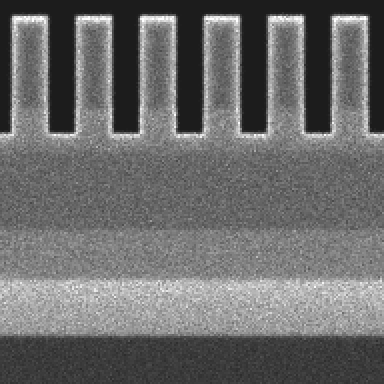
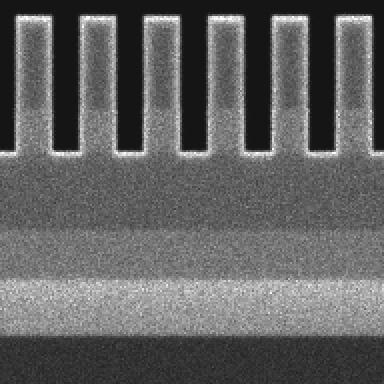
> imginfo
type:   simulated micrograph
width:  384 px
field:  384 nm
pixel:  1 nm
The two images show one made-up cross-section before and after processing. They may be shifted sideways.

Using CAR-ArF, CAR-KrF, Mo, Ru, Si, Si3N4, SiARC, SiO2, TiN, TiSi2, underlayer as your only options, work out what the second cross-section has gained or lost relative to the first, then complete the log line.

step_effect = removed TiN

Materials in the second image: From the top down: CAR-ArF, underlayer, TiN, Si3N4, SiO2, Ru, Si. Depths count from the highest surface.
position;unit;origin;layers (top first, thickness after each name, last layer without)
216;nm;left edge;CAR-ArF 44, underlayer 48, TiN 44, Si3N4 78, SiO2 50, Ru 56, Si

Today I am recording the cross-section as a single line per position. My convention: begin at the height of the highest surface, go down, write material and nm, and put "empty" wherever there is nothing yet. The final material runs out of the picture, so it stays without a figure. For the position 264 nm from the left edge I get empty 136, Si3N4 78, SiO2 50, Ru 56, Si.